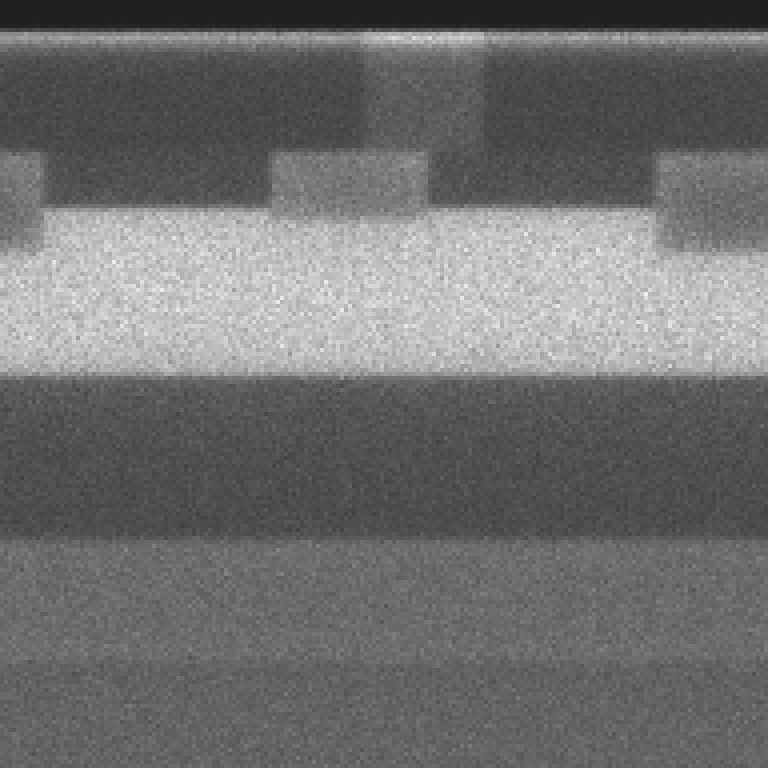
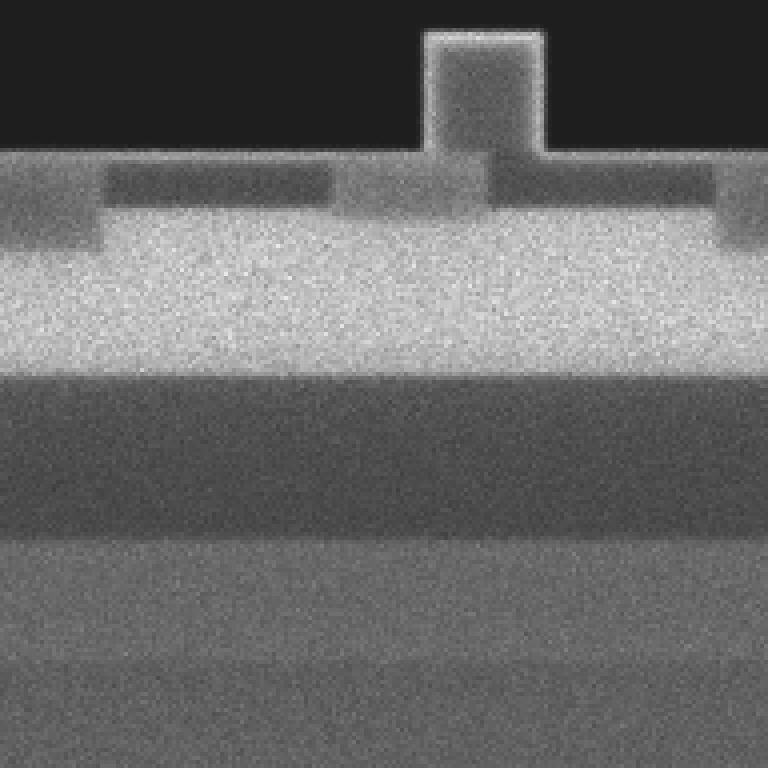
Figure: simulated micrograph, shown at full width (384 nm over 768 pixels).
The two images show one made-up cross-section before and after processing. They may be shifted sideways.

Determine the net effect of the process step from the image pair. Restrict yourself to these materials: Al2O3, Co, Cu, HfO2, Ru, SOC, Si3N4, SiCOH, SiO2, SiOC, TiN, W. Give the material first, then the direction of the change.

SOC: removed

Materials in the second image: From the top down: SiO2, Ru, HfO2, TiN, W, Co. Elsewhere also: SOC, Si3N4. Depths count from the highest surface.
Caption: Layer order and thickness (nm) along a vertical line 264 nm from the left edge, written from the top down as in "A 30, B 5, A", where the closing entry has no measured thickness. SiO2 60, Si3N4 28, HfO2 84, TiN 82, W 60, Co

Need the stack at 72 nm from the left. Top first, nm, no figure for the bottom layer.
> empty 60, Si3N4 28, HfO2 84, TiN 82, W 60, Co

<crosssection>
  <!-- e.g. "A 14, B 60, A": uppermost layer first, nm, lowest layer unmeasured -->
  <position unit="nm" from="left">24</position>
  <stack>empty 60, Ru 50, HfO2 62, TiN 82, W 60, Co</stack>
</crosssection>